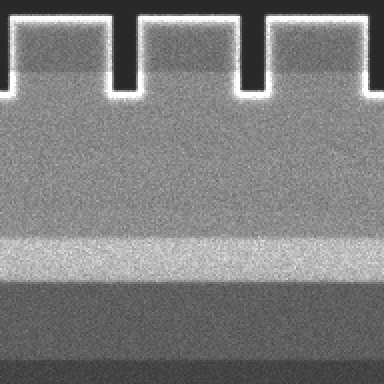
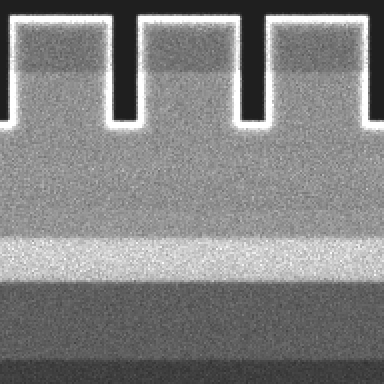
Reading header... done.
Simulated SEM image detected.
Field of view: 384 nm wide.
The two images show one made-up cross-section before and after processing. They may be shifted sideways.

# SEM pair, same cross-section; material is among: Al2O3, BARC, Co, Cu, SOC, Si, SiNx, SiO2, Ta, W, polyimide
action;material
removed;SiO2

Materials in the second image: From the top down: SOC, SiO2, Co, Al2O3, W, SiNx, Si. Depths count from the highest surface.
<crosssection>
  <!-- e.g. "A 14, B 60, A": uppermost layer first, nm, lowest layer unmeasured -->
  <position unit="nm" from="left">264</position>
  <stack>empty 106, SiO2 30, Co 58, Al2O3 28, W 44, SiNx 78, Si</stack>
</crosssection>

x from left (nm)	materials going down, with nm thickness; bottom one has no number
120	empty 106, SiO2 30, Co 58, Al2O3 28, W 44, SiNx 78, Si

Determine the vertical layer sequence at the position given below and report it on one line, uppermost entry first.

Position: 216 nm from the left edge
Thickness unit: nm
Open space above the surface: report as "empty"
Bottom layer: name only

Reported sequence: SOC 56, SiO2 80, Co 58, Al2O3 28, W 44, SiNx 78, Si